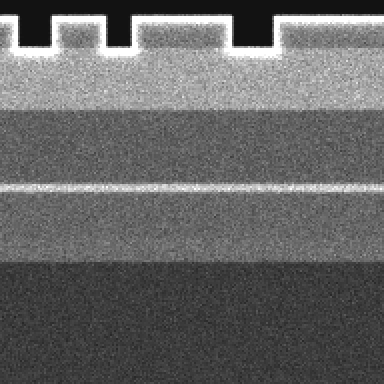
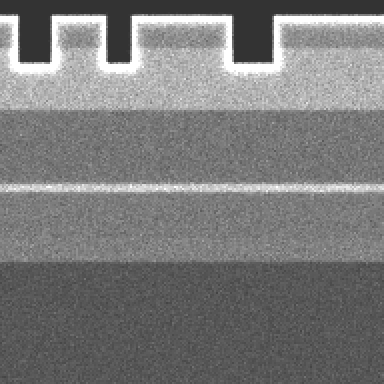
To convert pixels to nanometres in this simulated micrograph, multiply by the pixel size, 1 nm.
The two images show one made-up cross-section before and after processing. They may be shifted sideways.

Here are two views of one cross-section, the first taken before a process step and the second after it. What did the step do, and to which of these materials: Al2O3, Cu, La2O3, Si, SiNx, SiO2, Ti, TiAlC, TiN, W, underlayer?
It removed SiO2.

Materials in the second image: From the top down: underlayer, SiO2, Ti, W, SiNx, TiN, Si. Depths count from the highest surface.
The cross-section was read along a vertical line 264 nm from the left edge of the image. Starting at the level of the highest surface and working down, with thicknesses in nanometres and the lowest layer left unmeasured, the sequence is empty 48, SiO2 46, Ti 74, W 8, SiNx 46, TiN 24, Si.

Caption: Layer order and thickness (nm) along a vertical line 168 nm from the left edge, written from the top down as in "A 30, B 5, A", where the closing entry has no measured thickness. underlayer 32, SiO2 62, Ti 74, W 8, SiNx 46, TiN 24, Si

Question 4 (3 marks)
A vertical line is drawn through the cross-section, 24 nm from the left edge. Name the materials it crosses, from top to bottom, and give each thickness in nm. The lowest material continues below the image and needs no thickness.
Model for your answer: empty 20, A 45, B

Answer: empty 48, SiO2 46, Ti 74, W 8, SiNx 46, TiN 24, Si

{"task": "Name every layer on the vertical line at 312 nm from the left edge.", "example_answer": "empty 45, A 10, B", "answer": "underlayer 32, SiO2 62, Ti 74, W 8, SiNx 46, TiN 24, Si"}